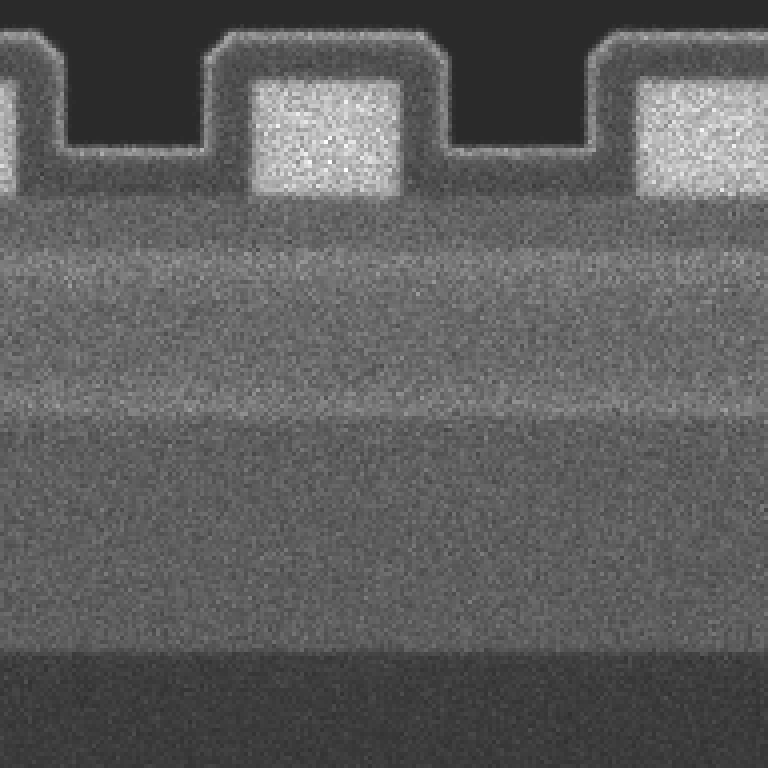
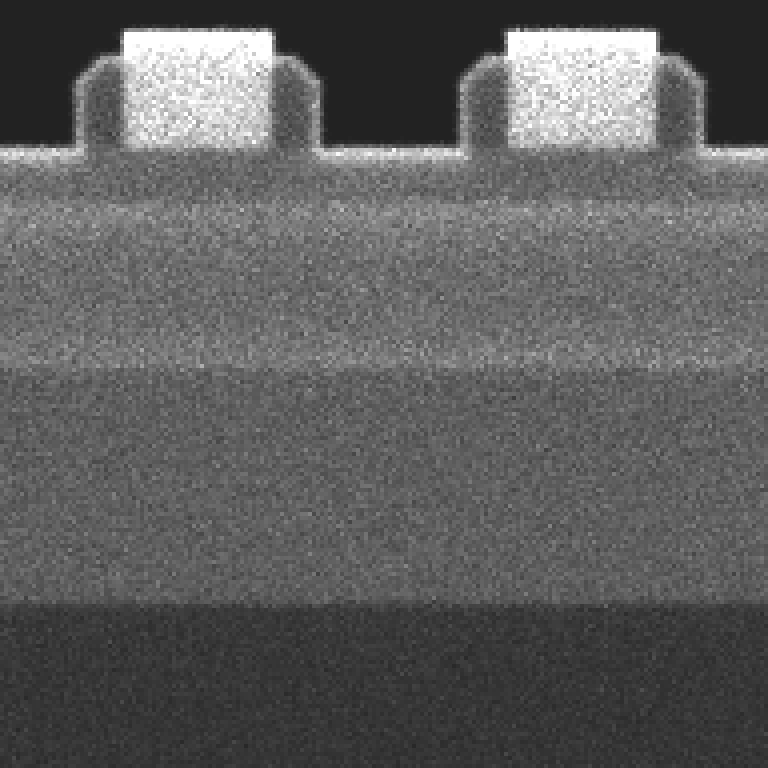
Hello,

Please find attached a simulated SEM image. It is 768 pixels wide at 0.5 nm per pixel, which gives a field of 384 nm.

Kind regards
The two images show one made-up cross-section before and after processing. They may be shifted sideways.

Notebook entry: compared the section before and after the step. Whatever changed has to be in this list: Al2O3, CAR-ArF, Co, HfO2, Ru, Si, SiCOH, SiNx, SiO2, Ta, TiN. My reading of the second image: SiNx removed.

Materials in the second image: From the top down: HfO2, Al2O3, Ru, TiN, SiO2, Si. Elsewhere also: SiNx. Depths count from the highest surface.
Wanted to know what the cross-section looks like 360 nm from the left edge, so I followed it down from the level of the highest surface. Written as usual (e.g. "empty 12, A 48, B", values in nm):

empty 58, Al2O3 28, Ru 82, TiN 10, SiO2 108, Si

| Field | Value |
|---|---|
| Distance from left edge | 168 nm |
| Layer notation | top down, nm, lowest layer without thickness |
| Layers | empty 58, Al2O3 28, Ru 82, TiN 10, SiO2 108, Si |